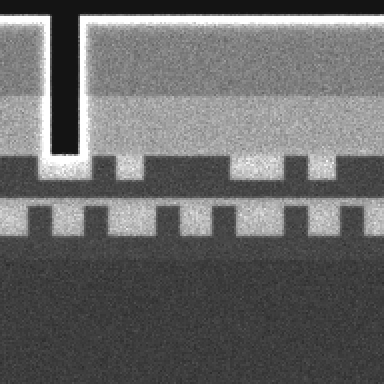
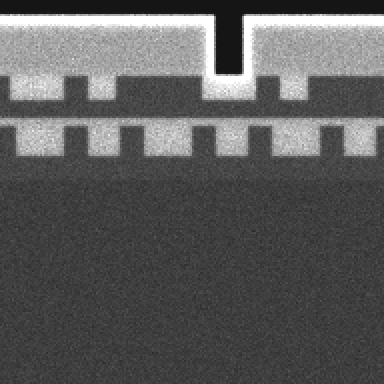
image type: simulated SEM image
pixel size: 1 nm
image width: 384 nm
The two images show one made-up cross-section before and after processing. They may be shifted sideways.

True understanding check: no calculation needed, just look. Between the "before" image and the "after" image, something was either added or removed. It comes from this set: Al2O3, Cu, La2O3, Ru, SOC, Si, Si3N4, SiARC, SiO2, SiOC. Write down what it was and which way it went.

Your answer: SOC (removed)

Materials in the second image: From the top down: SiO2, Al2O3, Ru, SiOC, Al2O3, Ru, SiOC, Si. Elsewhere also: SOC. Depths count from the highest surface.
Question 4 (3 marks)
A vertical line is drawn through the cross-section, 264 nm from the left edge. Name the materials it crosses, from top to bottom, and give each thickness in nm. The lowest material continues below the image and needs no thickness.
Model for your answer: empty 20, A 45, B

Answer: SiO2 52, Al2O3 8, SiOC 42, Al2O3 8, SiOC 54, Si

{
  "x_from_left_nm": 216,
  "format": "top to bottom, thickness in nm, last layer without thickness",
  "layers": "empty 60, Ru 24, SiOC 18, Al2O3 8, Ru 30, SiOC 24, Si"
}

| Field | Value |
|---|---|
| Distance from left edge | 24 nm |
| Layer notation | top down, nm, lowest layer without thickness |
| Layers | SiO2 52, Al2O3 8, Ru 24, SiOC 18, Al2O3 8, Ru 30, SiOC 24, Si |